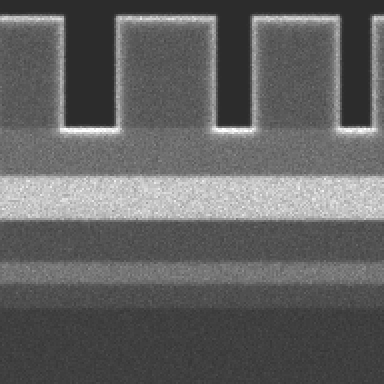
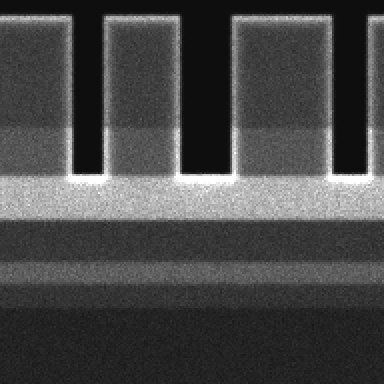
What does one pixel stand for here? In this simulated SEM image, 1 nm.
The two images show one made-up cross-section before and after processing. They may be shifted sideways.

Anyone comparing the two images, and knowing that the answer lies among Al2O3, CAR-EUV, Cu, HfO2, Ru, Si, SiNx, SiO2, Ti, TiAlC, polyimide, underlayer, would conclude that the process removed SiO2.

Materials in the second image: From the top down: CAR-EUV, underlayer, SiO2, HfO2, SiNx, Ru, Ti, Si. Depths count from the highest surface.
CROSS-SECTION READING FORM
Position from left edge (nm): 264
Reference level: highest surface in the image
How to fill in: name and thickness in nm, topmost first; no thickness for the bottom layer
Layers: CAR-EUV 54, underlayer 58, SiO2 48, HfO2 44, SiNx 42, Ru 22, Ti 24, Si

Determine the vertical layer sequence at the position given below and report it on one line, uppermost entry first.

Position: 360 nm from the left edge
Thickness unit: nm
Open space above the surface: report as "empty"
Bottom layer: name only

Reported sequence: empty 160, HfO2 44, SiNx 42, Ru 22, Ti 24, Si